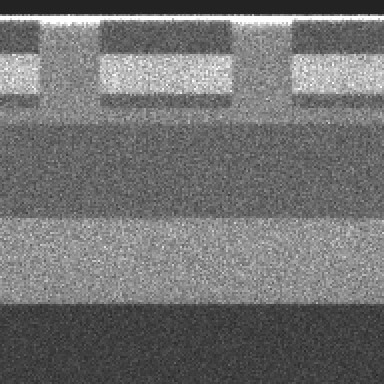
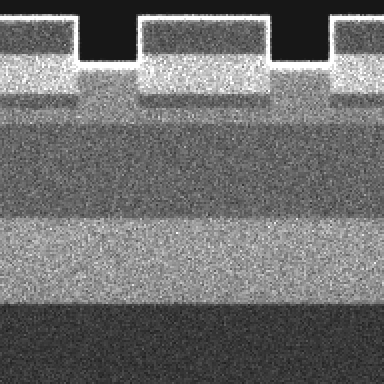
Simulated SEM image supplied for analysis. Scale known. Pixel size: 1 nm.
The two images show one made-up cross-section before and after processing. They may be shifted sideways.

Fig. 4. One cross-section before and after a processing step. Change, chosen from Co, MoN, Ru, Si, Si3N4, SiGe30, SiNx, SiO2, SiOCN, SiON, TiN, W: SiO2 removed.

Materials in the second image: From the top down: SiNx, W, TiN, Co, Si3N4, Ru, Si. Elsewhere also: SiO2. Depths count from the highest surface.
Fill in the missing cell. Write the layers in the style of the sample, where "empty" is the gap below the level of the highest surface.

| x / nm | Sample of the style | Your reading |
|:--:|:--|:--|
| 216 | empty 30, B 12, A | SiNx 38, W 40, TiN 14, Co 16, Si3N4 94, Ru 86, Si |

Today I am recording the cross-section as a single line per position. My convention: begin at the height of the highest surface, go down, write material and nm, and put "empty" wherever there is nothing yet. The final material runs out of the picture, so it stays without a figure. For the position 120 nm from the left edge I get empty 46, SiO2 62, Si3N4 94, Ru 86, Si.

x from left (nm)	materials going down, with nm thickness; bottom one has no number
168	SiNx 38, W 40, TiN 14, Co 16, Si3N4 94, Ru 86, Si